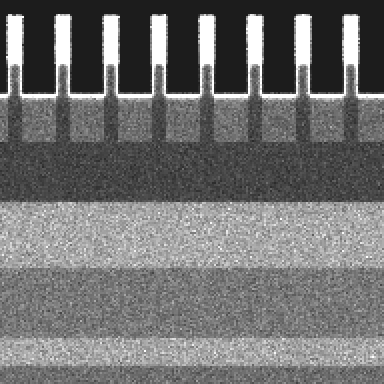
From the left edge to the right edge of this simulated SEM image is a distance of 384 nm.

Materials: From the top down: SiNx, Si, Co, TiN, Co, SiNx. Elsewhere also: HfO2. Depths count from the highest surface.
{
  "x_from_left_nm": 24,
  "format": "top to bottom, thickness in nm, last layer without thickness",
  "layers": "empty 78, SiNx 48, Si 60, Co 66, TiN 70, Co 28, SiNx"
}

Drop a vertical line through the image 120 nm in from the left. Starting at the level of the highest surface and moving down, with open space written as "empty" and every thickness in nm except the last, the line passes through empty 78, SiNx 48, Si 60, Co 66, TiN 70, Co 28, SiNx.